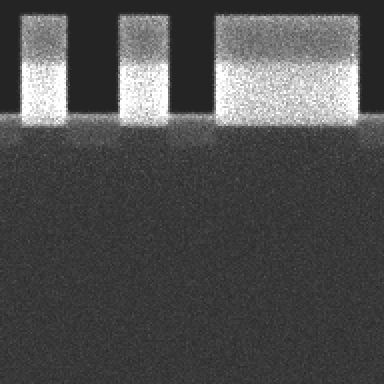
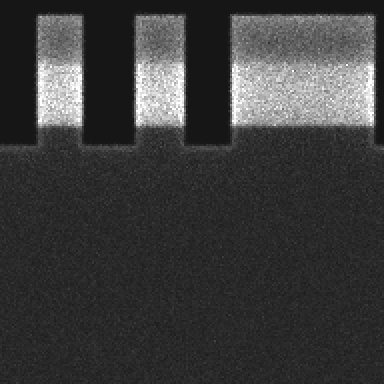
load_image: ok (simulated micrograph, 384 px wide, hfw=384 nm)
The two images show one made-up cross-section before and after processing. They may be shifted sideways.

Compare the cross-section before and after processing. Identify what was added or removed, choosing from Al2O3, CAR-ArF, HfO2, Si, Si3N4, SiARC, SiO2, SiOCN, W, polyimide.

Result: SiARC removed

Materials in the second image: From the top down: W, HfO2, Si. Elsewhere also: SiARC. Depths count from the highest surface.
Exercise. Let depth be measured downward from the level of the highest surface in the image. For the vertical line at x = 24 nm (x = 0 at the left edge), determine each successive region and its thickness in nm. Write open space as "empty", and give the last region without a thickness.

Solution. empty 130, Si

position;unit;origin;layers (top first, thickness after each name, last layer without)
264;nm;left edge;W 48, HfO2 62, Si